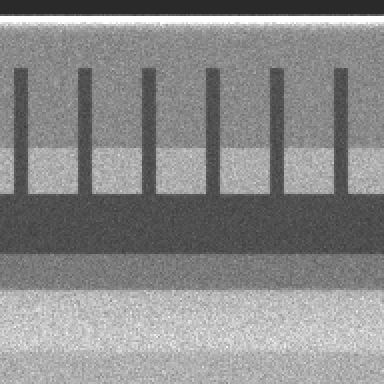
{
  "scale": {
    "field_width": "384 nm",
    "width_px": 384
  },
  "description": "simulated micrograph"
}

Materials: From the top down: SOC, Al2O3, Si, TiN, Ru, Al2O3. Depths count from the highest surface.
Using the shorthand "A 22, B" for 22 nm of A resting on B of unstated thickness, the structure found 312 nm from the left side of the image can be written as SOC 132, Al2O3 46, Si 60, TiN 36, Ru 62, Al2O3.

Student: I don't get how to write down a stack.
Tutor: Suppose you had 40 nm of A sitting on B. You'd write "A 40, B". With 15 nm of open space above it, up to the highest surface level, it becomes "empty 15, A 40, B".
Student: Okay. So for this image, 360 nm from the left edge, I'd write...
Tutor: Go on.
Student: SOC 132, Al2O3 46, Si 60, TiN 36, Ru 62, Al2O3